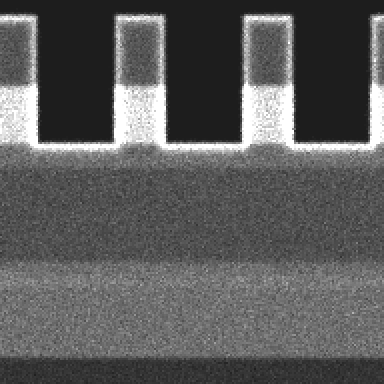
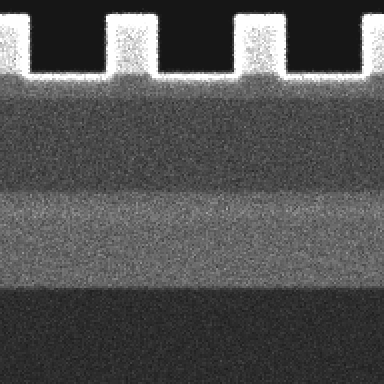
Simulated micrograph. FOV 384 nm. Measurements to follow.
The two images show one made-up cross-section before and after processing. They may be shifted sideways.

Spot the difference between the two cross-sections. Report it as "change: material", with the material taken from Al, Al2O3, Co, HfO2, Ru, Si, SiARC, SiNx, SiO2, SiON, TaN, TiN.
removed: SiARC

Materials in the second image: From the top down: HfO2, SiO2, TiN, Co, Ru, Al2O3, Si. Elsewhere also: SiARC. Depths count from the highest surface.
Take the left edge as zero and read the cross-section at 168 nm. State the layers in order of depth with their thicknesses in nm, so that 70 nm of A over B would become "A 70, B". empty 58, SiO2 24, TiN 94, Co 14, Ru 12, Al2O3 70, Si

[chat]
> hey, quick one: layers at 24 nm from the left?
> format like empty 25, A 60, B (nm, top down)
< HfO2 58, SiO2 24, TiN 94, Co 14, Ru 12, Al2O3 70, Si